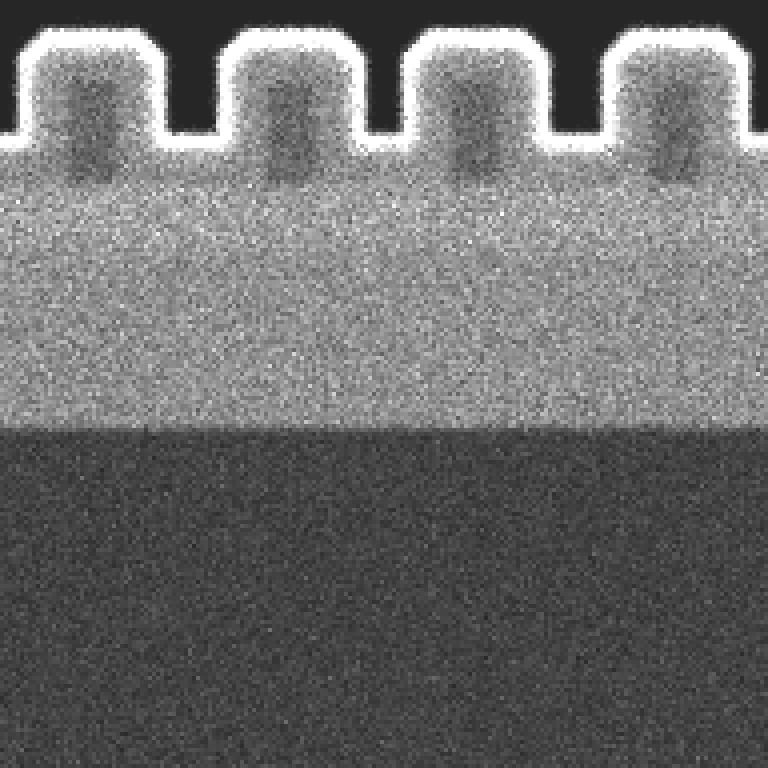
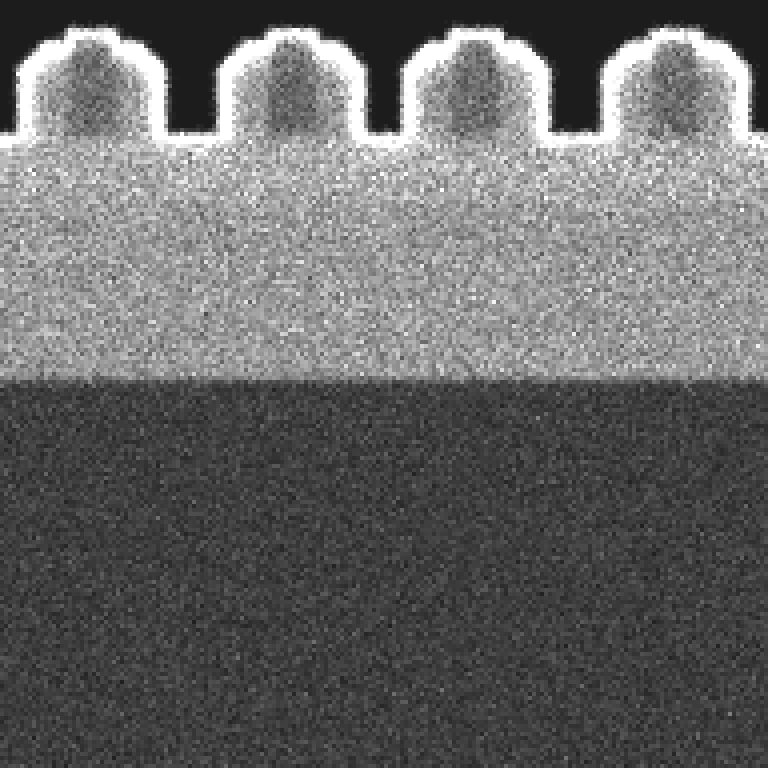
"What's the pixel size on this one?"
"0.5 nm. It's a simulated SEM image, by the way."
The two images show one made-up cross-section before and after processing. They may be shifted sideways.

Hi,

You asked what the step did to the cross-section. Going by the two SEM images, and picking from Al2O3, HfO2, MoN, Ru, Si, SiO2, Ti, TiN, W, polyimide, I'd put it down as SiO2, removed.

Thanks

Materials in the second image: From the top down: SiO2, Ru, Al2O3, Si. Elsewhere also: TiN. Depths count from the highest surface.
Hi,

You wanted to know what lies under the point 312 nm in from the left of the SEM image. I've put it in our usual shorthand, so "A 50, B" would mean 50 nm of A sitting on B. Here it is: empty 8, SiO2 44, Ru 34, Al2O3 88, Si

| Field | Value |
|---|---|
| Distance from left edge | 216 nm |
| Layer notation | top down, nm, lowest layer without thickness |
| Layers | empty 6, SiO2 46, Ru 34, Al2O3 88, Si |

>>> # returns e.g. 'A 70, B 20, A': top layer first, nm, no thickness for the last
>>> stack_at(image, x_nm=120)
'empty 8, SiO2 44, Ru 34, Al2O3 88, Si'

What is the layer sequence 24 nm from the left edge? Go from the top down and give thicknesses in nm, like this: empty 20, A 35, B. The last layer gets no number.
empty 6, SiO2 46, Ru 34, Al2O3 88, Si